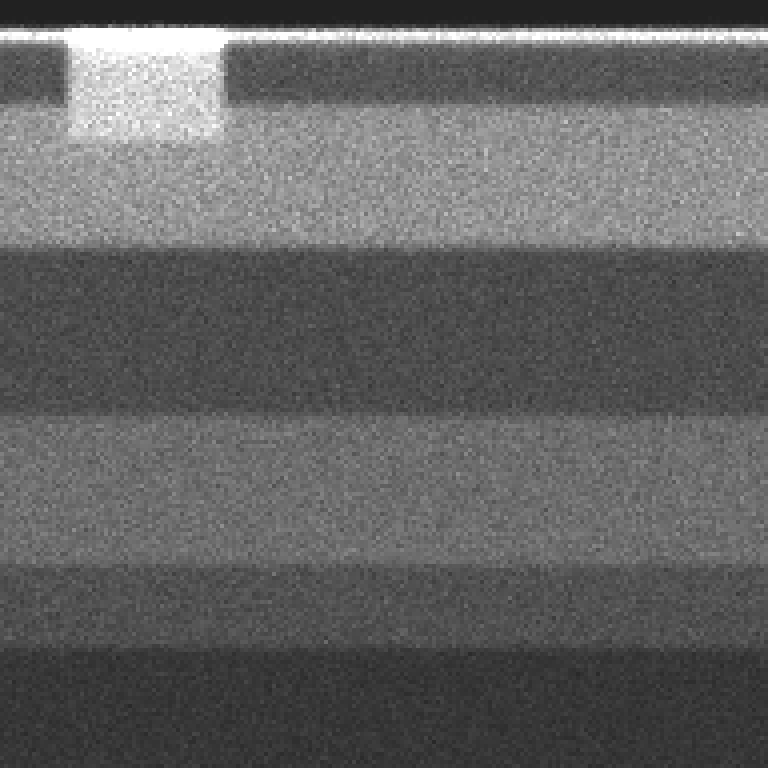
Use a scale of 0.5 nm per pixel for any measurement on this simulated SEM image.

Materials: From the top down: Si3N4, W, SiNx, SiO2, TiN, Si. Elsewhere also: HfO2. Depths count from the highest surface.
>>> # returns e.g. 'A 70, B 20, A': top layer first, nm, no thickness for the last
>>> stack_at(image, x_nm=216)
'Si3N4 36, W 72, SiNx 84, SiO2 74, TiN 42, Si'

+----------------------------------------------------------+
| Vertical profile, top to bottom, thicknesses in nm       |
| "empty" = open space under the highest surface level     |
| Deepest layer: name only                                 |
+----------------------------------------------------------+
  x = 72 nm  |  HfO2 54, W 54, SiNx 84, SiO2 74, TiN 42, Si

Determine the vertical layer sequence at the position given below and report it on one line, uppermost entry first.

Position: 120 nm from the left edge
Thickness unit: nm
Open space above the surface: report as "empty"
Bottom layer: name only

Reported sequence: Si3N4 36, W 72, SiNx 84, SiO2 74, TiN 42, Si